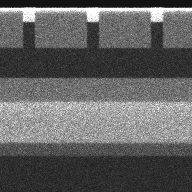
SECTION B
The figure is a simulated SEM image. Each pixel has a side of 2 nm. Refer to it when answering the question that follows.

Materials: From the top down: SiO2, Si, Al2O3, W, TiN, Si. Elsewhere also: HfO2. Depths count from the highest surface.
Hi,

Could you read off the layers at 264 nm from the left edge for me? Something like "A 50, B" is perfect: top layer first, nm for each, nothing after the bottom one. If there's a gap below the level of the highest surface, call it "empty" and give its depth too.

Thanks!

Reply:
SiO2 80, Si 60, Al2O3 48, W 82, TiN 26, Si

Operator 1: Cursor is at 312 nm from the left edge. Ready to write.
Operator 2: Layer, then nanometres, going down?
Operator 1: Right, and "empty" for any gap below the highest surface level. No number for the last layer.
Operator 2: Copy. HfO2 28, Si 112, Al2O3 48, W 82, TiN 26, Si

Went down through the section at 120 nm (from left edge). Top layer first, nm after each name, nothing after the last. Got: SiO2 80, Si 60, Al2O3 48, W 82, TiN 26, Si